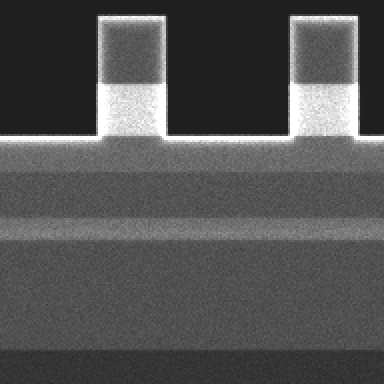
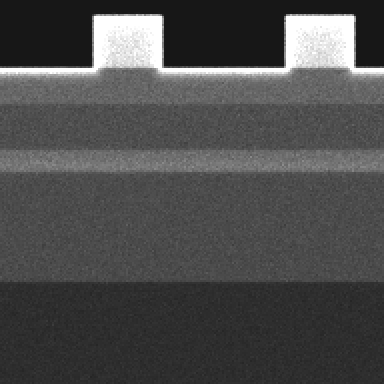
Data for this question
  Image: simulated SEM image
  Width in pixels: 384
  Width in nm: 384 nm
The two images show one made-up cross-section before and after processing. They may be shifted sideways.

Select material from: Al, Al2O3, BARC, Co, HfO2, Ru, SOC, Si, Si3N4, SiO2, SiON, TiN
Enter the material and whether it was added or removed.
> SOC / removed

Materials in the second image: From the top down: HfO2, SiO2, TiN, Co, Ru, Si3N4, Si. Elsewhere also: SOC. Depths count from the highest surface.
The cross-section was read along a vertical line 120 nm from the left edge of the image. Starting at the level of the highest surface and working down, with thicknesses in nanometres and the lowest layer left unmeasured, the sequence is HfO2 52, SiO2 36, TiN 46, Co 12, Ru 10, Si3N4 110, Si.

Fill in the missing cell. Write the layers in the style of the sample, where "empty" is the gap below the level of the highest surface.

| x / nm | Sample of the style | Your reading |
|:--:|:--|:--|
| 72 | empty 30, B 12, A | empty 52, SiO2 36, TiN 46, Co 12, Ru 10, Si3N4 110, Si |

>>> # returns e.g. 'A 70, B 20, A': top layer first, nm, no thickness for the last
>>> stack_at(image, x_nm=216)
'empty 52, SiO2 36, TiN 46, Co 12, Ru 10, Si3N4 110, Si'